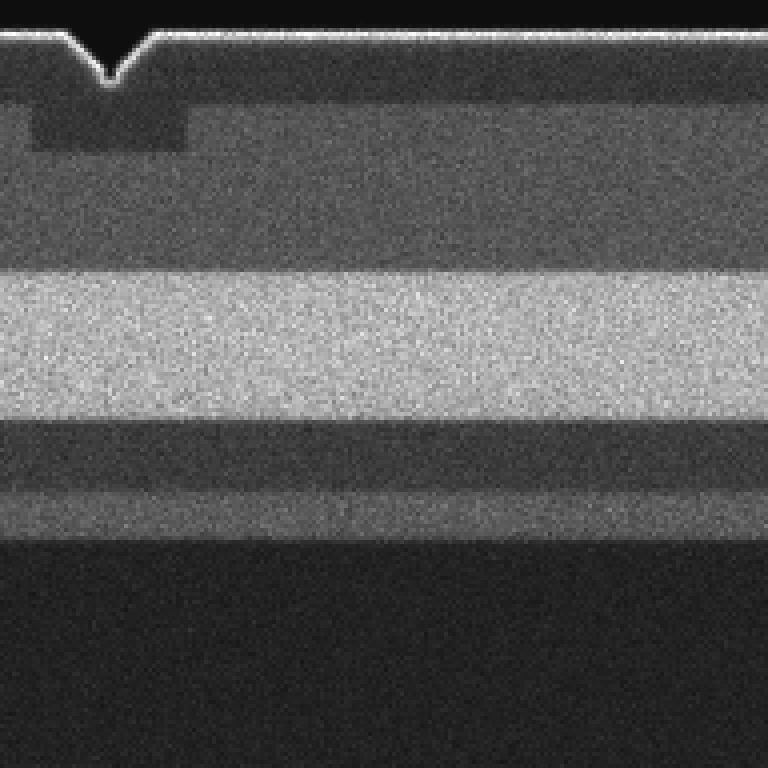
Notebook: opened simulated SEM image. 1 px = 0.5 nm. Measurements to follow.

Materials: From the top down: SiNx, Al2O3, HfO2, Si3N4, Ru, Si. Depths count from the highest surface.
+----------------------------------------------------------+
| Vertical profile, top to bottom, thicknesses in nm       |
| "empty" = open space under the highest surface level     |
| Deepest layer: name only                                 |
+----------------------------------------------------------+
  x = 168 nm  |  SiNx 36, Al2O3 84, HfO2 74, Si3N4 36, Ru 24, Si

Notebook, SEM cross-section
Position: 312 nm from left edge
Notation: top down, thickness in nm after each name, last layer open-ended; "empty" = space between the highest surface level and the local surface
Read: SiNx 36, Al2O3 84, HfO2 74, Si3N4 36, Ru 24, Si